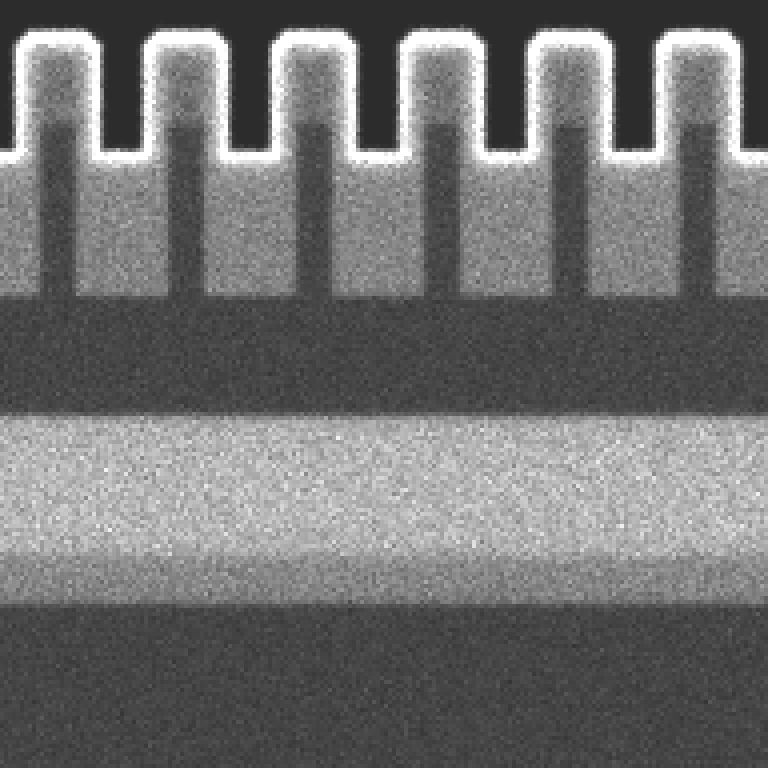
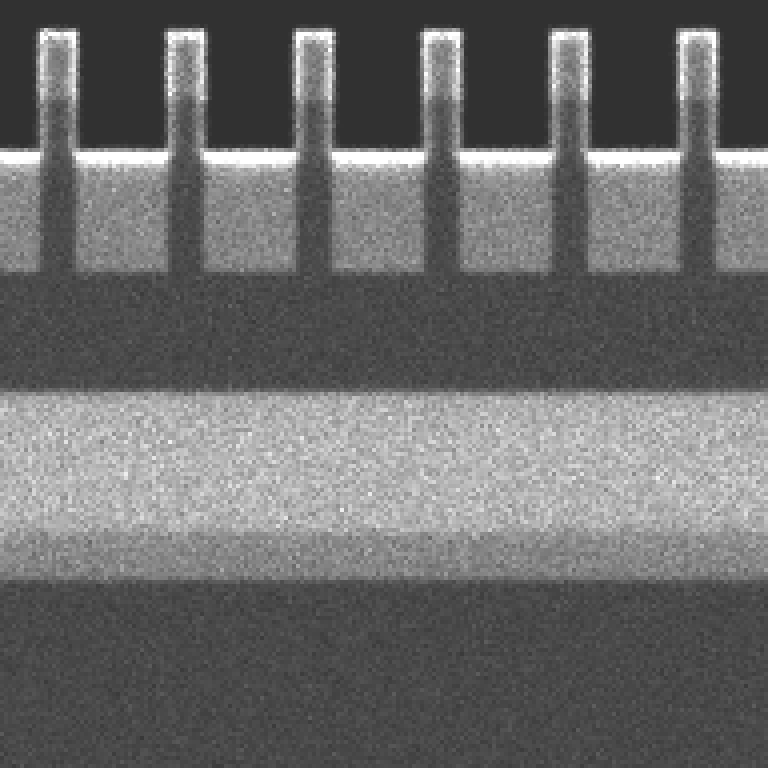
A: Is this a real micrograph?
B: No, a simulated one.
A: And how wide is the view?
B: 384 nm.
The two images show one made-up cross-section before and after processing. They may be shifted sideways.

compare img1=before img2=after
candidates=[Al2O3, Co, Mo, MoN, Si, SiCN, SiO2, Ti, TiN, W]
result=removed:SiO2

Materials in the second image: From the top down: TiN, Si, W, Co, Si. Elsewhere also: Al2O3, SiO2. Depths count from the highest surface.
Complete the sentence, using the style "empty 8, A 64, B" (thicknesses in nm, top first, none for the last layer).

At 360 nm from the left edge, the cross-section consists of empty 60, Al2O3 60, Si 60, W 70, Co 24, Si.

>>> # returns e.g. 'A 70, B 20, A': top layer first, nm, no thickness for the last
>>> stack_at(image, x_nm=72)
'empty 60, Al2O3 60, Si 60, W 70, Co 24, Si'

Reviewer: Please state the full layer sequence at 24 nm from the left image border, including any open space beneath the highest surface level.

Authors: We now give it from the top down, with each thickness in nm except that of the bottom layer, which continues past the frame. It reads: TiN 34, Si 146, W 70, Co 24, Si